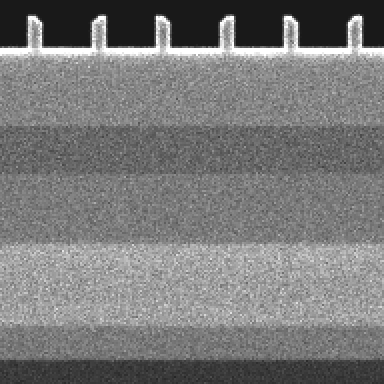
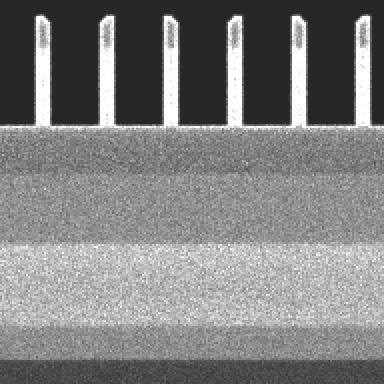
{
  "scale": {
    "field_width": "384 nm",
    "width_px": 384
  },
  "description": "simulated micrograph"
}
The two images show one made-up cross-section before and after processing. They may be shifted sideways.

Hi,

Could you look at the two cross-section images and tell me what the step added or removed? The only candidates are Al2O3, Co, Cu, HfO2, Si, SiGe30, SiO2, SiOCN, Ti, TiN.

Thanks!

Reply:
removed Al2O3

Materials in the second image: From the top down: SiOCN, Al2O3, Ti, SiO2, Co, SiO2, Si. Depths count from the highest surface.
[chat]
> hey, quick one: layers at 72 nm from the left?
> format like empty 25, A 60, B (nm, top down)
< empty 110, Ti 48, SiO2 70, Co 82, SiO2 34, Si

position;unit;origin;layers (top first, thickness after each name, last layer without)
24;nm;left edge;empty 110, Ti 48, SiO2 70, Co 82, SiO2 34, Si